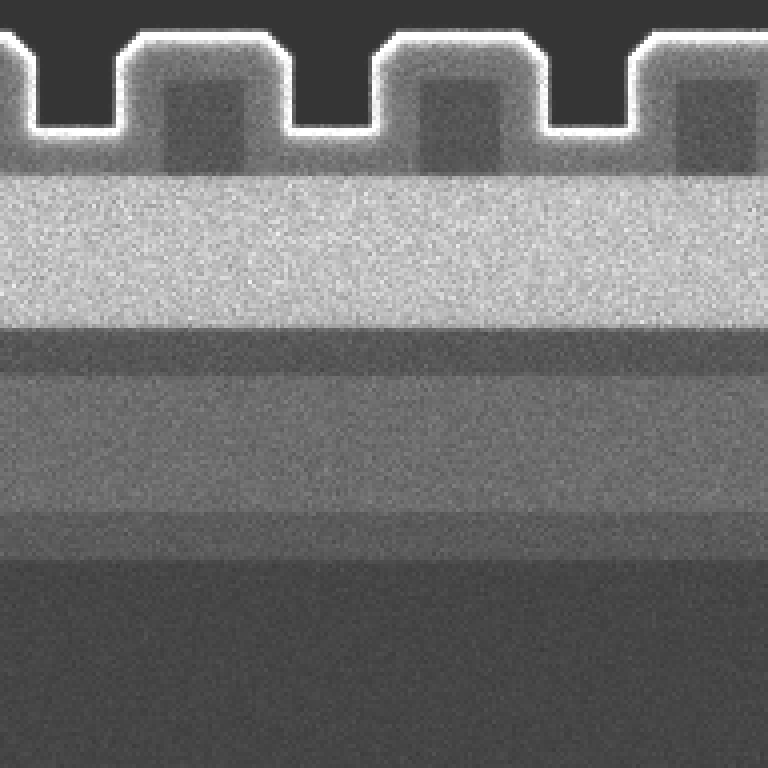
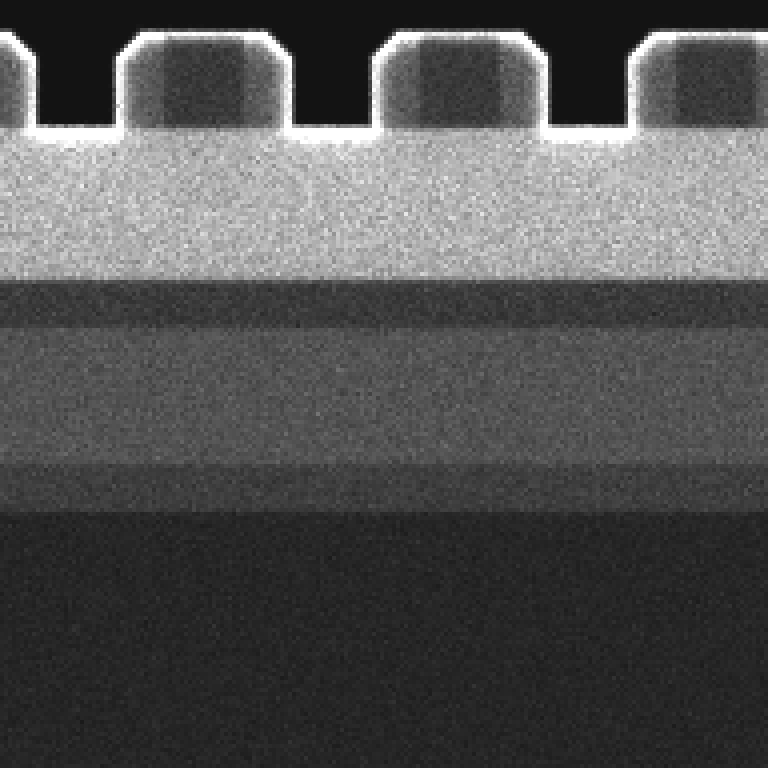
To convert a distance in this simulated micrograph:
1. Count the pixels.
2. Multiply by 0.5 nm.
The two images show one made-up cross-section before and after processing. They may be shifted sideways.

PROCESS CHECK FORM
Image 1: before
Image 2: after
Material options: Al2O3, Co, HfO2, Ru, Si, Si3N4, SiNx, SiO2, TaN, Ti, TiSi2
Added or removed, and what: removed, Al2O3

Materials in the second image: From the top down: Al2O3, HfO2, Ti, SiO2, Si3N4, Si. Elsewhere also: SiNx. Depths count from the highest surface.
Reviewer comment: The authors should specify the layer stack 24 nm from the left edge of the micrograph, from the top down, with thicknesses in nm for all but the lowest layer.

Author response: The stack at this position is empty 48, HfO2 76, Ti 24, SiO2 68, Si3N4 24, Si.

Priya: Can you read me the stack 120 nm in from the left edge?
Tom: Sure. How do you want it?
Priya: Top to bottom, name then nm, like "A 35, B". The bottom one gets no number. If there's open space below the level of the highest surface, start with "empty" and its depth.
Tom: SiNx 48, HfO2 76, Ti 24, SiO2 68, Si3N4 24, Si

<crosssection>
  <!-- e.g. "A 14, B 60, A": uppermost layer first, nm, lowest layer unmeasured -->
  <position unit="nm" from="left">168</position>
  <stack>empty 48, HfO2 76, Ti 24, SiO2 68, Si3N4 24, Si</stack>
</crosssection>